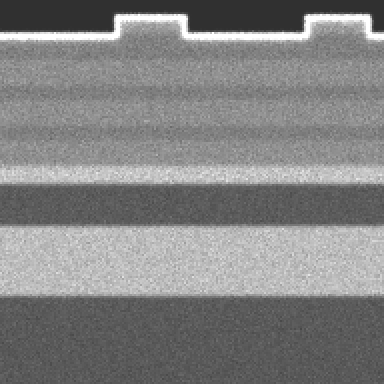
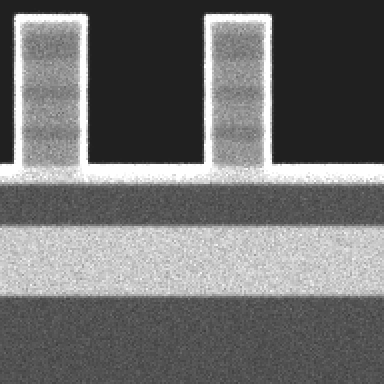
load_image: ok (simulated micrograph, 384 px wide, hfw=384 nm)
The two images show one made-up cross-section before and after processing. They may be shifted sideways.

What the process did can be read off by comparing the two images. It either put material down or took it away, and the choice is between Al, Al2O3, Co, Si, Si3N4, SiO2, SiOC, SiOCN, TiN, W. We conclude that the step removed Si3N4 and SiOCN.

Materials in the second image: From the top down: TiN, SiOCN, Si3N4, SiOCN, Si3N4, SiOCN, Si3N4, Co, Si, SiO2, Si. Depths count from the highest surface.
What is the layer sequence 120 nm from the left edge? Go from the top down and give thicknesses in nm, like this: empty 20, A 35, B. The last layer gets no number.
empty 150, Co 18, Si 42, SiO2 70, Si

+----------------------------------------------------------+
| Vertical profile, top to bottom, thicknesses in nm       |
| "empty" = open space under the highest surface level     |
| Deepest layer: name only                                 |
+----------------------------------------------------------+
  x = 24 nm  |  TiN 18, SiOCN 26, Si3N4 26, SiOCN 14, Si3N4 26, SiOCN 14, Si3N4 26, Co 18, Si 42, SiO2 70, Si